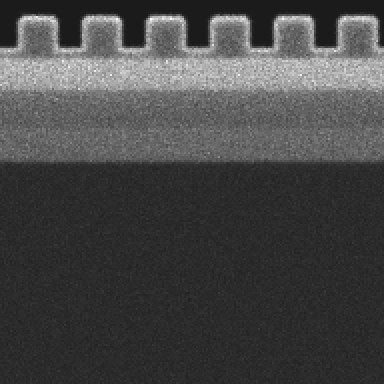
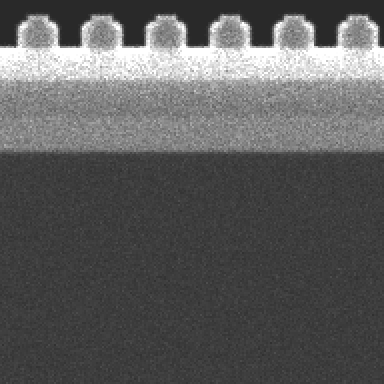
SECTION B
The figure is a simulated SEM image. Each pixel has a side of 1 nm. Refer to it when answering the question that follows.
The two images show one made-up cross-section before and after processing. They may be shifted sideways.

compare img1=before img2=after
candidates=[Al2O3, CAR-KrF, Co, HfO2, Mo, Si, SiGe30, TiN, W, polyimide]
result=removed:Al2O3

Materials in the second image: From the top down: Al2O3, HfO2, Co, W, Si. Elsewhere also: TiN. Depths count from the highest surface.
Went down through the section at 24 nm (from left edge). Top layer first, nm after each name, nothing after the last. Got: empty 6, Al2O3 26, HfO2 32, Co 38, W 34, Si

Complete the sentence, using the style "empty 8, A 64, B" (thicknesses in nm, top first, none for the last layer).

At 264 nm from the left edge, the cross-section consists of empty 32, HfO2 32, Co 38, W 34, Si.